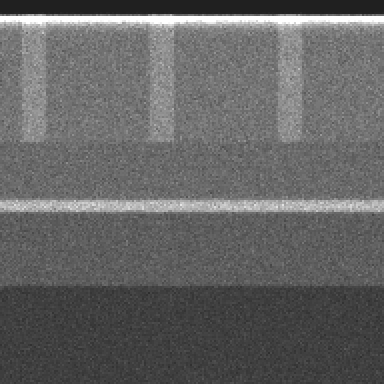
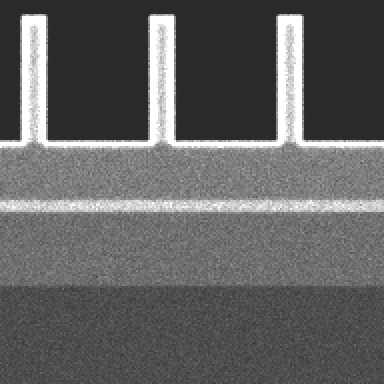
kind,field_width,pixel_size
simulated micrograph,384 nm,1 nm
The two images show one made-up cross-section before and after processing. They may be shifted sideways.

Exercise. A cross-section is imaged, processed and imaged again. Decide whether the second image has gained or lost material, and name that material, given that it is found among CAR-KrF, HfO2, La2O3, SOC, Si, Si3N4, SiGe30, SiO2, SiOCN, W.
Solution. removed: SOC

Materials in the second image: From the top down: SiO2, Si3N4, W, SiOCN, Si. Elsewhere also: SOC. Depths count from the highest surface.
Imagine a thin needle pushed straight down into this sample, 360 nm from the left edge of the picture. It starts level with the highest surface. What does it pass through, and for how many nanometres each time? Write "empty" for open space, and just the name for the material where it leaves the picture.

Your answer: empty 126, Si3N4 58, W 12, SiOCN 74, Si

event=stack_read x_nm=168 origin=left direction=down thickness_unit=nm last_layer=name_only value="SiO2 126, Si3N4 58, W 12, SiOCN 74, Si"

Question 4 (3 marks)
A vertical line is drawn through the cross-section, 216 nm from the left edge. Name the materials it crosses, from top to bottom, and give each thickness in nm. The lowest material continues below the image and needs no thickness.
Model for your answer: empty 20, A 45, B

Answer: empty 126, Si3N4 58, W 12, SiOCN 74, Si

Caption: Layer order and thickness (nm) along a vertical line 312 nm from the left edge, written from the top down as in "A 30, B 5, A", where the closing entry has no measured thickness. empty 126, Si3N4 58, W 12, SiOCN 74, Si